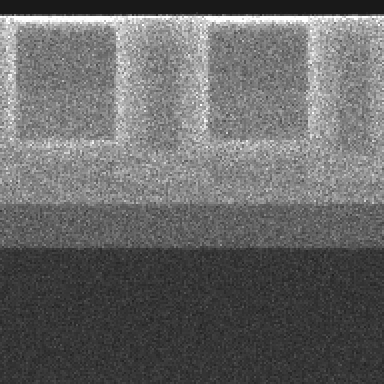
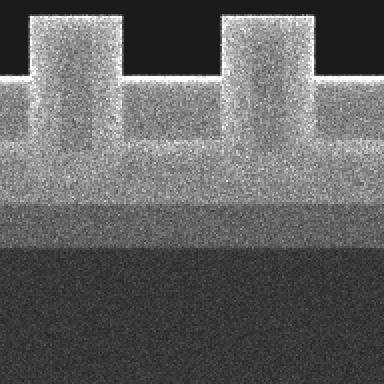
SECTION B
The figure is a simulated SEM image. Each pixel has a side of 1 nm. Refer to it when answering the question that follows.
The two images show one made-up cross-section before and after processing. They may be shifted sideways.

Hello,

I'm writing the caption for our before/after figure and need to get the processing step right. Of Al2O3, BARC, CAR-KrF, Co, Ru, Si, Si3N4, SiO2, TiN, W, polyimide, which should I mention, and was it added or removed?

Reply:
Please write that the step removed SiO2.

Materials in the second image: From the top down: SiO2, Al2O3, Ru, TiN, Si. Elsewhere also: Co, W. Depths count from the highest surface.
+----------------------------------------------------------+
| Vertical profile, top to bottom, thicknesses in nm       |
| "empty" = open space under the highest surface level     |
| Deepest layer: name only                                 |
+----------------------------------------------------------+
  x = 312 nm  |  W 166, Ru 22, TiN 44, Si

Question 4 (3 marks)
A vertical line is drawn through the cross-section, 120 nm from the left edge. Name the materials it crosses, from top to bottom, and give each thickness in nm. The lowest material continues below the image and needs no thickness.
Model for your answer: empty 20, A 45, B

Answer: W 166, Ru 22, TiN 44, Si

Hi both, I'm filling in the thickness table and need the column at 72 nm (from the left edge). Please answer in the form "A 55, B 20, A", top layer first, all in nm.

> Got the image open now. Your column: Co 136, W 30, Ru 22, TiN 44, Si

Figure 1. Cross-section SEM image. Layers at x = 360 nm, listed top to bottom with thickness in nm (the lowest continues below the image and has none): empty 60, SiO2 14, Al2O3 50, Ru 64, TiN 44, Si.